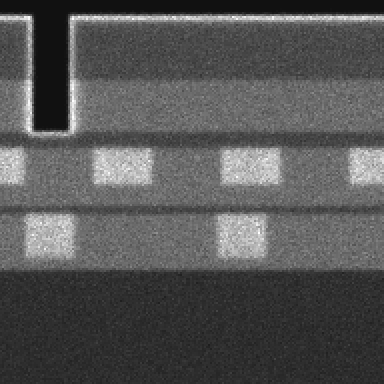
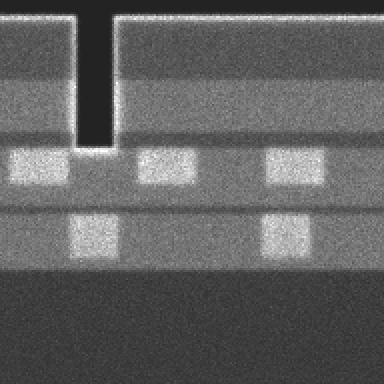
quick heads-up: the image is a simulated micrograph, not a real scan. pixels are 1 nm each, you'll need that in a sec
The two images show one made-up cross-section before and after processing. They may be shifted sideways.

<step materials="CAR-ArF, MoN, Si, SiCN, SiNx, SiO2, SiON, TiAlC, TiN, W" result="removed SiCN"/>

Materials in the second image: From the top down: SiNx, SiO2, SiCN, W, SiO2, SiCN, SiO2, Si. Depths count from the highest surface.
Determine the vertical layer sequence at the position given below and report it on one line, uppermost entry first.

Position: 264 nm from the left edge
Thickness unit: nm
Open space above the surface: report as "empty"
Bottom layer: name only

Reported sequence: SiNx 64, SiO2 52, SiCN 16, SiO2 58, SiCN 8, W 44, SiO2 12, Si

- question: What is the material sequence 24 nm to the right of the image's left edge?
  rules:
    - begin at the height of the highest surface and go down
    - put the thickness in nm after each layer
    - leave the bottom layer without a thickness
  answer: SiNx 64, SiO2 52, SiCN 16, W 36, SiO2 22, SiCN 8, SiO2 56, Si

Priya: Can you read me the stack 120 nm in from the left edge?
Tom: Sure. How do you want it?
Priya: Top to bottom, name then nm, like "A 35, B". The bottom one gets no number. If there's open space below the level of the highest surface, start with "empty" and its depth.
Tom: SiNx 64, SiO2 52, SiCN 16, SiO2 58, SiCN 8, SiO2 56, Si